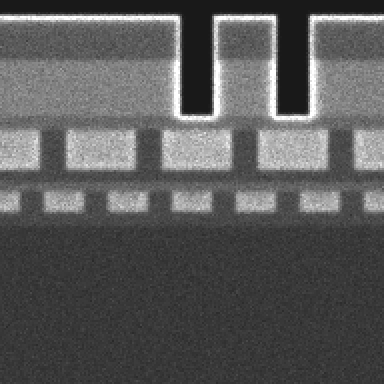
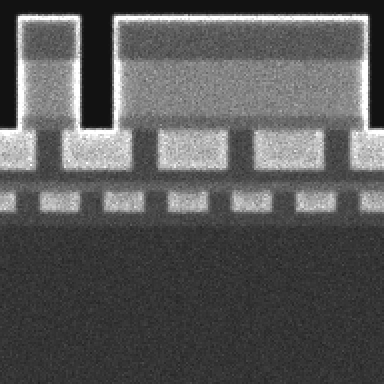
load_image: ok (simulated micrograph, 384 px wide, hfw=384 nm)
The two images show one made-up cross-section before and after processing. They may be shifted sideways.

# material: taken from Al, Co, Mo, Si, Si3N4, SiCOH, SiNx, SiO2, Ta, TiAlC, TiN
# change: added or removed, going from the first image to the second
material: Si3N4
change: removed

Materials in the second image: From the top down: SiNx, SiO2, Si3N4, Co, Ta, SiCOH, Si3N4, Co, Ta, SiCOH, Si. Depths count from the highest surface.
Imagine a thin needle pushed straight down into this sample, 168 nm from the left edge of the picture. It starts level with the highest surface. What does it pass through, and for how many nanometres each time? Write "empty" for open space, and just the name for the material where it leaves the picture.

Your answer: SiNx 44, SiO2 56, Si3N4 14, Co 32, Ta 8, SiCOH 12, Si3N4 10, Ta 20, SiCOH 14, Si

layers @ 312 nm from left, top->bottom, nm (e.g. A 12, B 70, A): SiNx 44, SiO2 56, Si3N4 14, Co 32, Ta 8, SiCOH 12, Si3N4 10, Co 12, Ta 8, SiCOH 14, Si